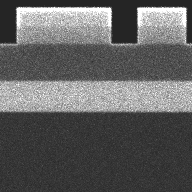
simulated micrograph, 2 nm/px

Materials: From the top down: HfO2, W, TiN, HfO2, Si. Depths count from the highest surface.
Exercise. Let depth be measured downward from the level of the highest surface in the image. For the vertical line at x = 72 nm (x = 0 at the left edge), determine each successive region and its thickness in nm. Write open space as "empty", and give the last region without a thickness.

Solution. HfO2 36, W 36, TiN 74, HfO2 62, Si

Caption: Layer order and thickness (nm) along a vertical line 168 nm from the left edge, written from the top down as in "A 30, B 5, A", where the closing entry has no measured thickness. HfO2 36, W 36, TiN 74, HfO2 62, Si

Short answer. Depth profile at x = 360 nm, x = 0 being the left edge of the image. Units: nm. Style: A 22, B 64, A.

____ HfO2 36, W 36, TiN 74, HfO2 62, Si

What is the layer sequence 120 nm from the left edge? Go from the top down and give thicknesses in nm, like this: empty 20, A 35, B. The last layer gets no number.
HfO2 36, W 36, TiN 74, HfO2 62, Si